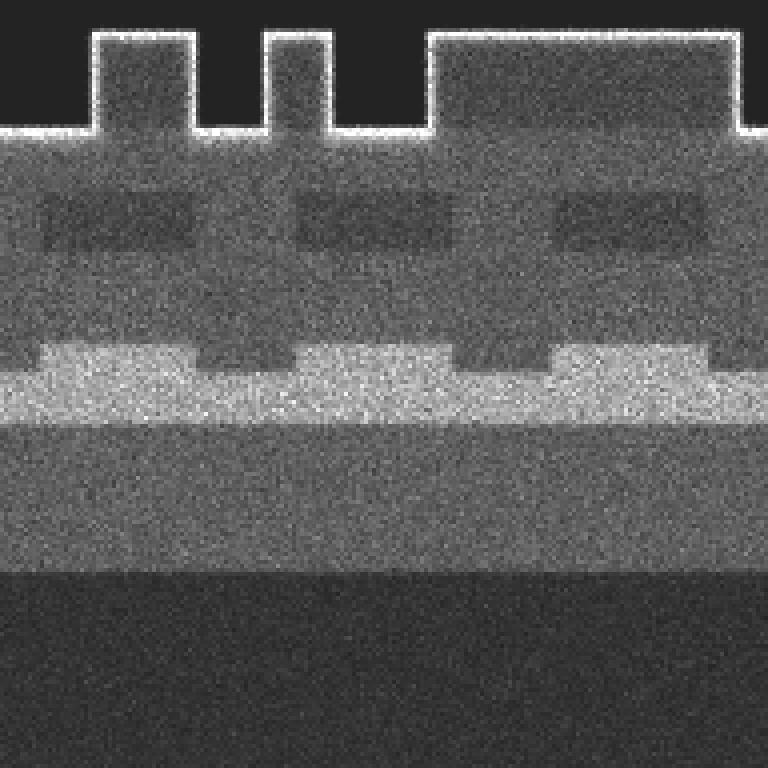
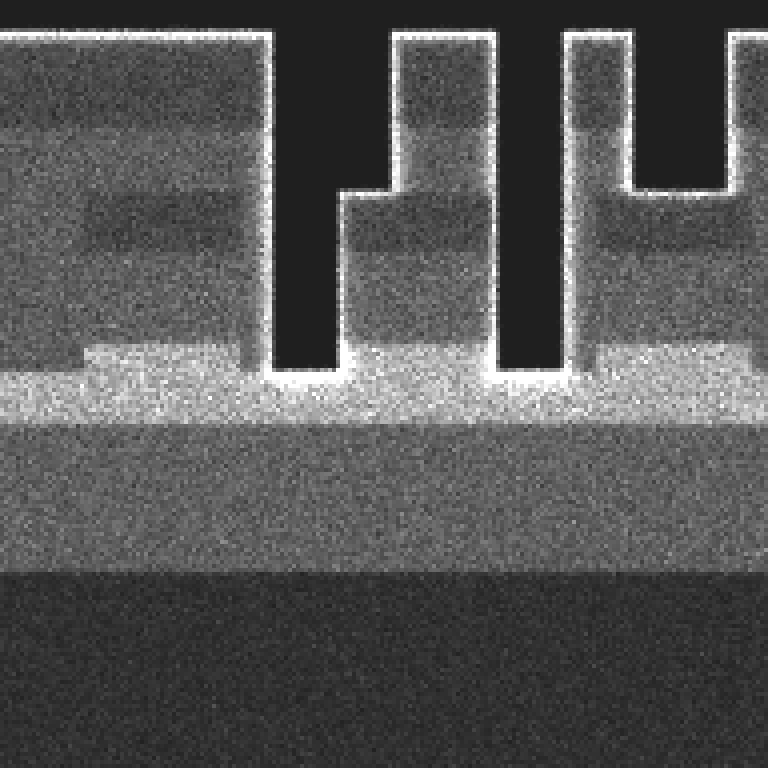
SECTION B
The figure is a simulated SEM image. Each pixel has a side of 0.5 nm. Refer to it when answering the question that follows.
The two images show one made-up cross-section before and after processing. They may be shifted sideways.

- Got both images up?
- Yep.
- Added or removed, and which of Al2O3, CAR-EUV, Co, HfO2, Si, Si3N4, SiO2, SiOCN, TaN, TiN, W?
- removed, SiO2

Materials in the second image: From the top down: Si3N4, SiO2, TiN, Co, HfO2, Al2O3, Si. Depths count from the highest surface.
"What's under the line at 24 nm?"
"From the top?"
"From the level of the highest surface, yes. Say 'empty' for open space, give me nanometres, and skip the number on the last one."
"Si3N4 48, SiO2 122, HfO2 26, Al2O3 74, Si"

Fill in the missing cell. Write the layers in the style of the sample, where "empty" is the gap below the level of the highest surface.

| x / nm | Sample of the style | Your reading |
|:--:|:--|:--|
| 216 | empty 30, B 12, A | Si3N4 48, SiO2 32, TiN 30, Co 46, HfO2 40, Al2O3 74, Si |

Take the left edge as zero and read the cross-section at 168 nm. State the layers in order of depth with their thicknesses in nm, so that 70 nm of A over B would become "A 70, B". empty 170, HfO2 26, Al2O3 74, Si